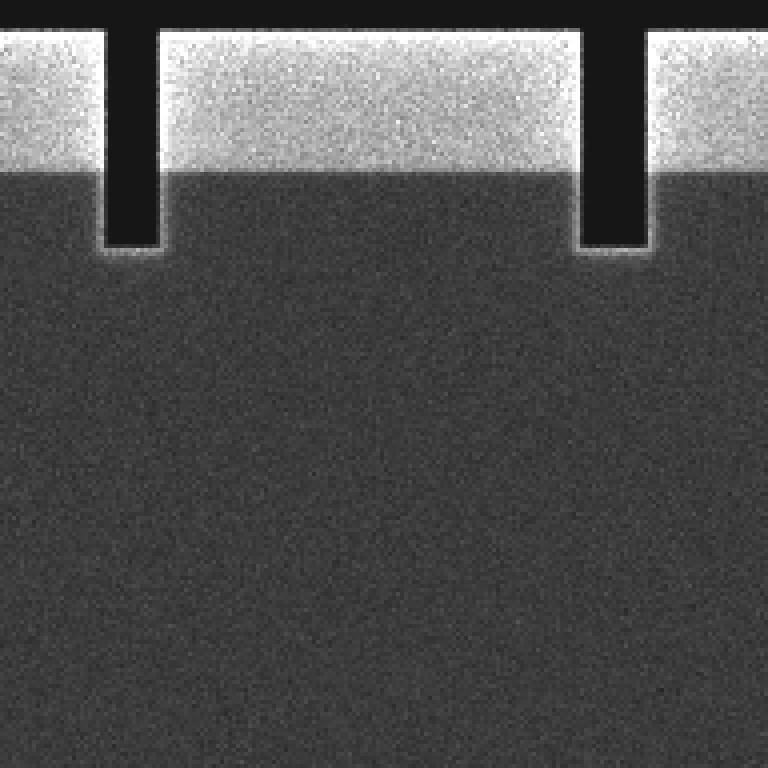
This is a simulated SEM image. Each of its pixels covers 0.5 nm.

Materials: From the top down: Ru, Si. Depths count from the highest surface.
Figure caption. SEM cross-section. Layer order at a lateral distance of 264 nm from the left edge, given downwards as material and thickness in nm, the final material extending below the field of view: Ru 70, Si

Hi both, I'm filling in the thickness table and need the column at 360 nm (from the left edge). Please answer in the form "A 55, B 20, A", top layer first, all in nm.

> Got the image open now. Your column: Ru 70, Si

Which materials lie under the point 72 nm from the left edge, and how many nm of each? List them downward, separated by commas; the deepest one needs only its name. empty 108, Si